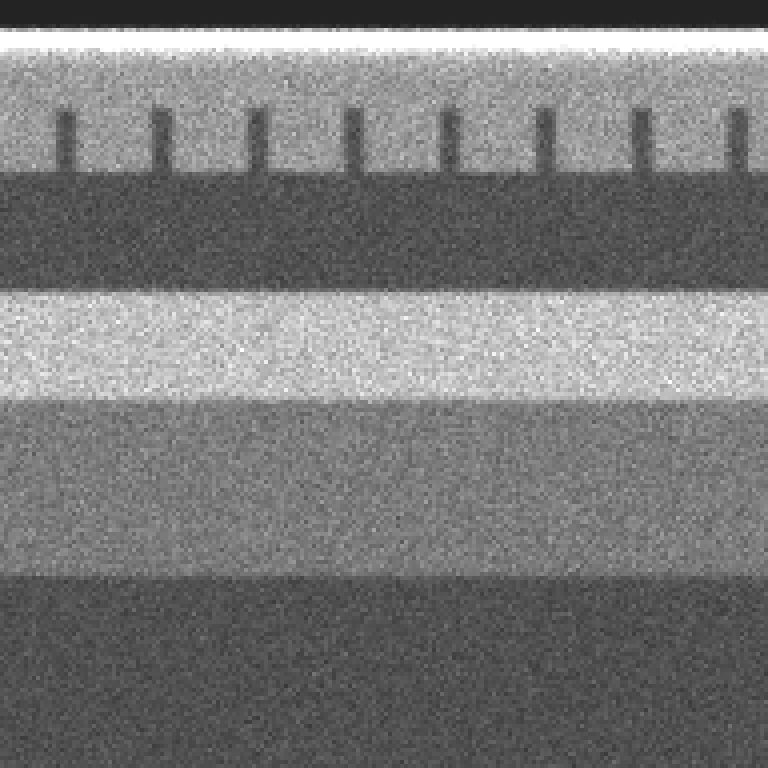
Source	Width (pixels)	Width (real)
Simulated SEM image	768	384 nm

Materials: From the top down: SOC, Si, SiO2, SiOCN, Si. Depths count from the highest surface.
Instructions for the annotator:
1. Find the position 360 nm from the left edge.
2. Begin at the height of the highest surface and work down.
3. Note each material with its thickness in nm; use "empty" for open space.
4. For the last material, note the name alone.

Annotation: SOC 70, Si 60, SiO2 54, SiOCN 88, Si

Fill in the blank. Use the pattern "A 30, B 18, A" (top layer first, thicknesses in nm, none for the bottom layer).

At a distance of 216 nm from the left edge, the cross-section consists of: SOC 70, Si 60, SiO2 54, SiOCN 88, Si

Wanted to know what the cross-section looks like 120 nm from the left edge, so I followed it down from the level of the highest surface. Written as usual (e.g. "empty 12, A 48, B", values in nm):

SOC 70, Si 60, SiO2 54, SiOCN 88, Si